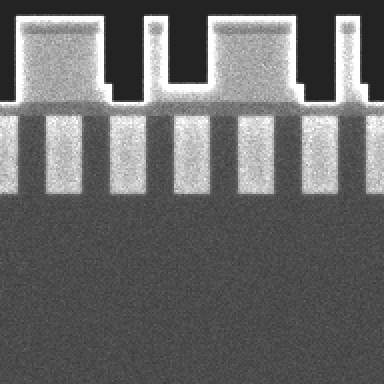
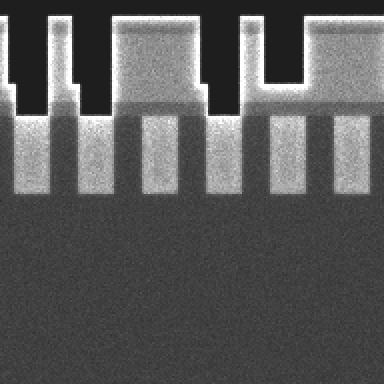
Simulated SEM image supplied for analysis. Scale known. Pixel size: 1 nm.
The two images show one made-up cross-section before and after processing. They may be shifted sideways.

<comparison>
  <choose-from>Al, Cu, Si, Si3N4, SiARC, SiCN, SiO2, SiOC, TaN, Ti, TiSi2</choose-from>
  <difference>SiCN removed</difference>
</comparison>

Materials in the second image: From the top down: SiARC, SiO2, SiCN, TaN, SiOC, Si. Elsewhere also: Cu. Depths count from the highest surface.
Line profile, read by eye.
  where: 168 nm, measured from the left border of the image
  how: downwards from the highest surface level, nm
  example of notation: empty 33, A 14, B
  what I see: SiARC 18, SiO2 68, SiCN 14, TaN 78, SiOC 26, Si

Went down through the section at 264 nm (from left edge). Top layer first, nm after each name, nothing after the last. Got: empty 68, SiO2 18, SiCN 14, SiOC 104, Si